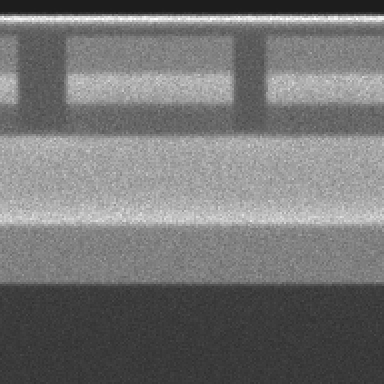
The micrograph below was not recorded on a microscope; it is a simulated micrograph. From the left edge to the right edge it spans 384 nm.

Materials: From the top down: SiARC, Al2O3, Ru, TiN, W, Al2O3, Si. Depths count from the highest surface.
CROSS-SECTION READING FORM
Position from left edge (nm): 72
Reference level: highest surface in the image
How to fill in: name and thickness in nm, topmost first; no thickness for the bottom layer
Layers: SiARC 20, Al2O3 38, Ru 30, TiN 32, W 88, Al2O3 60, Si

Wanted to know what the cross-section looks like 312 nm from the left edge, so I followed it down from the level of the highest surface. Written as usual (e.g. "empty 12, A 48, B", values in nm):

SiARC 20, Al2O3 38, Ru 30, TiN 32, W 88, Al2O3 60, Si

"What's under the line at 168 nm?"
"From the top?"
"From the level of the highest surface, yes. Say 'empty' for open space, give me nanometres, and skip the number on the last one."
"SiARC 20, Al2O3 38, Ru 30, TiN 32, W 88, Al2O3 60, Si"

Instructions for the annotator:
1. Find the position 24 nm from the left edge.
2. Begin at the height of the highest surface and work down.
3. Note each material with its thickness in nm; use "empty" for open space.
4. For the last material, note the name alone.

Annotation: SiARC 114, TiN 6, W 88, Al2O3 60, Si